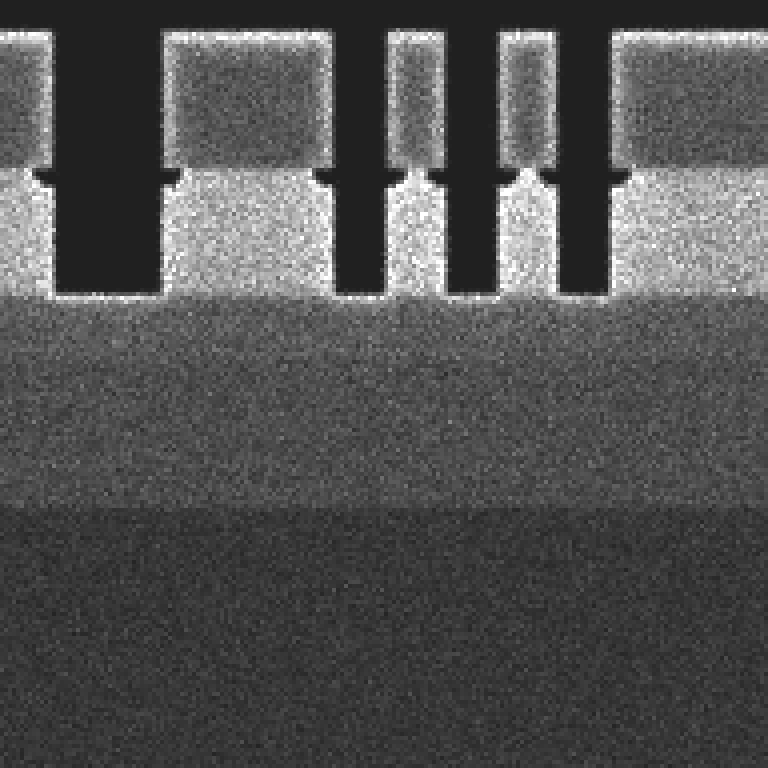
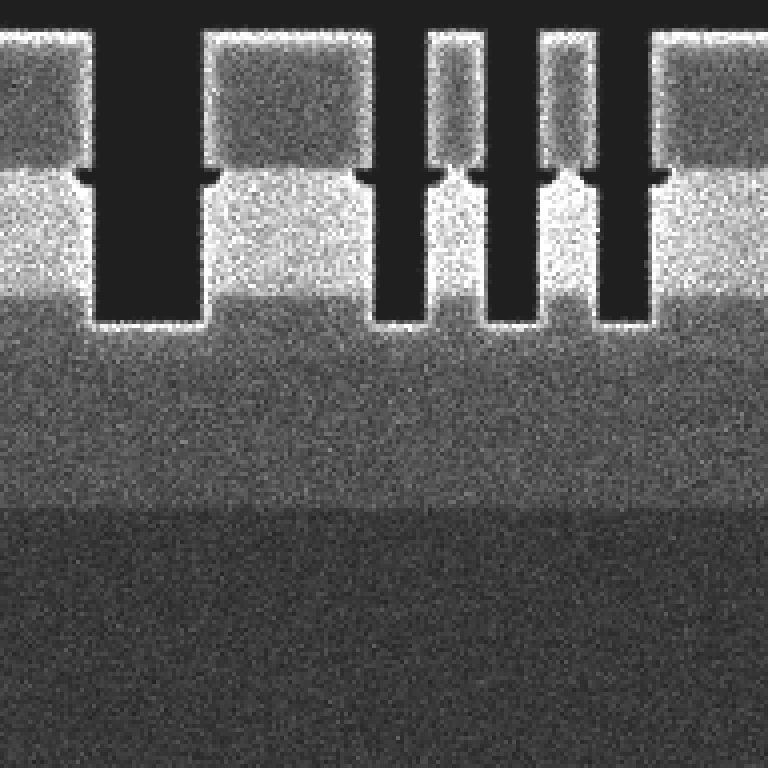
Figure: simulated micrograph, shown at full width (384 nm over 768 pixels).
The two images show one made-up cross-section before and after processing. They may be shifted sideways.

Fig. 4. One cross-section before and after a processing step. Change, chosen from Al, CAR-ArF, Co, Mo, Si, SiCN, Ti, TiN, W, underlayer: TiN removed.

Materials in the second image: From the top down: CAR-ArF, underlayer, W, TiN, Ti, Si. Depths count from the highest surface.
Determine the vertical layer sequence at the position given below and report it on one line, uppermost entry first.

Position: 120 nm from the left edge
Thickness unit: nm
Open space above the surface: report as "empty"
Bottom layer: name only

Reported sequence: CAR-ArF 50, underlayer 18, W 64, TiN 32, Ti 74, Si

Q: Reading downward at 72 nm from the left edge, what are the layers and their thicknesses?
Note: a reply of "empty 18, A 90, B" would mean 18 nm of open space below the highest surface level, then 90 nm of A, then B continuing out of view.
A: empty 146, TiN 18, Ti 74, Si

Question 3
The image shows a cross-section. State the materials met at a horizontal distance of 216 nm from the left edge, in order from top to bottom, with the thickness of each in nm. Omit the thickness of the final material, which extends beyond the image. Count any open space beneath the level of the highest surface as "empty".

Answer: CAR-ArF 50, underlayer 18, empty 10, W 54, TiN 32, Ti 74, Si